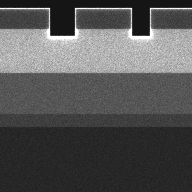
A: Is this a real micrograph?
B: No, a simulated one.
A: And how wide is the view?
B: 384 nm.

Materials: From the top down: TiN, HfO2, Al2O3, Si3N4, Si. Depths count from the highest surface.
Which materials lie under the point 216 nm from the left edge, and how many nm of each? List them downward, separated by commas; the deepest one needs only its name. TiN 42, HfO2 88, Al2O3 82, Si3N4 26, Si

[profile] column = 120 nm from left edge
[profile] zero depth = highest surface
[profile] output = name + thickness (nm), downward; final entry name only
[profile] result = empty 56, HfO2 74, Al2O3 82, Si3N4 26, Si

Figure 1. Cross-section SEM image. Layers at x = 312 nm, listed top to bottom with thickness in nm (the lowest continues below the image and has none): TiN 42, HfO2 88, Al2O3 82, Si3N4 26, Si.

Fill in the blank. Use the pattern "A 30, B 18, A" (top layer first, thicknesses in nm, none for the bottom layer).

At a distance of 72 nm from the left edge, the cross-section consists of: TiN 42, HfO2 88, Al2O3 82, Si3N4 26, Si